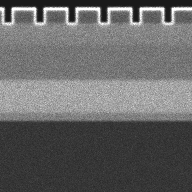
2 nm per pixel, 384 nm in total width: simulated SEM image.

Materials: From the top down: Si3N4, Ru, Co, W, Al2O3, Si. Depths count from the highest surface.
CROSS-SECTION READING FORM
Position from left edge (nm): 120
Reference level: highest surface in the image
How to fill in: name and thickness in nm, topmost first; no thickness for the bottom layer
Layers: Si3N4 30, Ru 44, Co 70, W 66, Al2O3 16, Si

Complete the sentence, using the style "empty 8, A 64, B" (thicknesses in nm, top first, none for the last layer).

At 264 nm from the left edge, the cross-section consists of empty 30, Ru 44, Co 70, W 66, Al2O3 16, Si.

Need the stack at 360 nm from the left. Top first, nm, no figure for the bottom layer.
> Si3N4 30, Ru 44, Co 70, W 66, Al2O3 16, Si